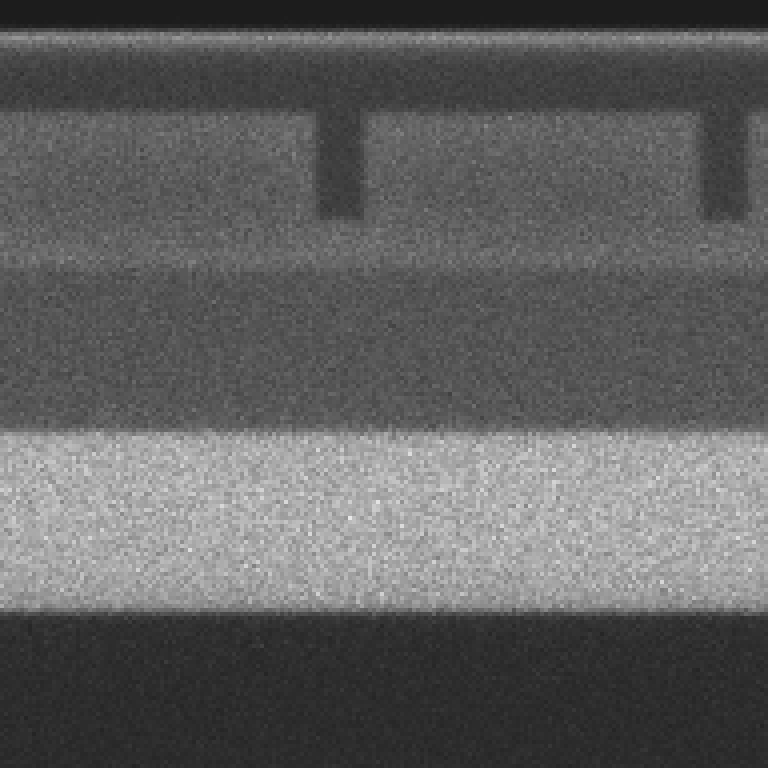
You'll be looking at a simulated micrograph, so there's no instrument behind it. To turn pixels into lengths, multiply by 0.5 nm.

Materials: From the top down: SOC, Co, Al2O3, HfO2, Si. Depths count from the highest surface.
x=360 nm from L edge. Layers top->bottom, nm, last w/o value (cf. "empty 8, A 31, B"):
SOC 94, Co 24, Al2O3 82, HfO2 90, Si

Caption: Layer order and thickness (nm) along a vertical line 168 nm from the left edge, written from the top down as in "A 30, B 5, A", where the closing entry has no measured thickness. SOC 94, Co 24, Al2O3 82, HfO2 90, Si